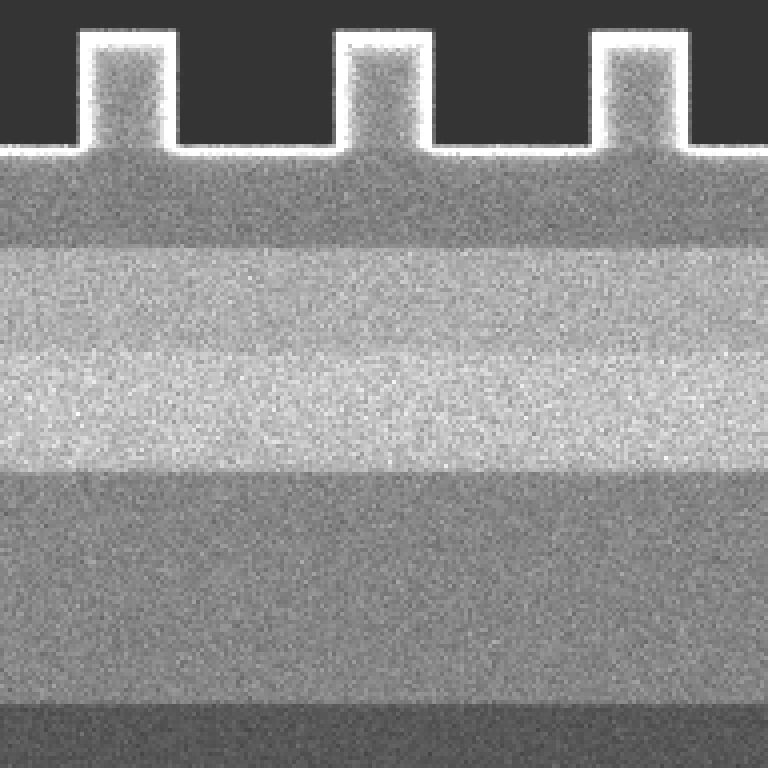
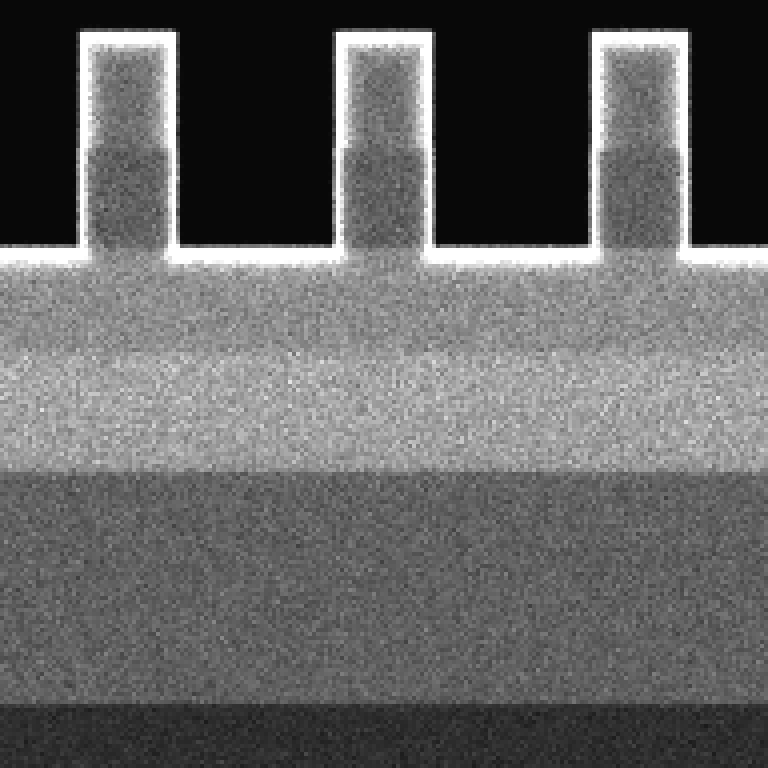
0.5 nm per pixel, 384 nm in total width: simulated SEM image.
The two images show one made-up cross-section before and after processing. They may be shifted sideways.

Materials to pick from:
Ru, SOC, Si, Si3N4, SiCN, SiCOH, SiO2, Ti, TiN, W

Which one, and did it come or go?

TiN - removed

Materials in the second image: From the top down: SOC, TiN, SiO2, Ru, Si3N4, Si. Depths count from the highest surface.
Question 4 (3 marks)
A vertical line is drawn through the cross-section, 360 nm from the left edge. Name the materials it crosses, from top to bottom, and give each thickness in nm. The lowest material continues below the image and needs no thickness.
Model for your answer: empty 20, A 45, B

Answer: empty 108, SiO2 52, Ru 60, Si3N4 116, Si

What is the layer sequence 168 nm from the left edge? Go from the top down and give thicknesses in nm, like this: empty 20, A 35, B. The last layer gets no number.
SOC 58, TiN 50, SiO2 52, Ru 60, Si3N4 116, Si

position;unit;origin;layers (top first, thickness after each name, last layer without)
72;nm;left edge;SOC 58, TiN 50, SiO2 52, Ru 60, Si3N4 116, Si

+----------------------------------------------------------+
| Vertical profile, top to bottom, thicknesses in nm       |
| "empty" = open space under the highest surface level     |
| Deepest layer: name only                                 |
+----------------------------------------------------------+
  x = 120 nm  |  empty 108, SiO2 52, Ru 60, Si3N4 116, Si